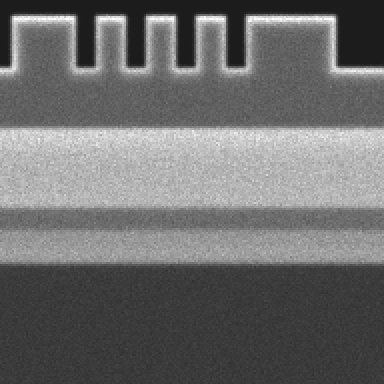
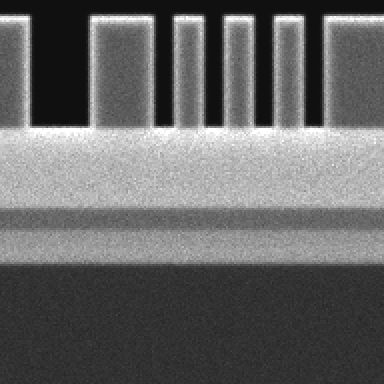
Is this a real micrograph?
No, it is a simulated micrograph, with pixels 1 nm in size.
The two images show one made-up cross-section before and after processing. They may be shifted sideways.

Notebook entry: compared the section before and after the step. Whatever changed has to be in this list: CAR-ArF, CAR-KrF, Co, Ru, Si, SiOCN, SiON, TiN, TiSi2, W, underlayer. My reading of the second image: underlayer removed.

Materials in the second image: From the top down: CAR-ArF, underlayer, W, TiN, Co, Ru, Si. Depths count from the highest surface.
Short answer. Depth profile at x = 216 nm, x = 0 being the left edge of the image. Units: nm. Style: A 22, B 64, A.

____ empty 112, W 80, TiN 22, Co 18, Ru 16, Si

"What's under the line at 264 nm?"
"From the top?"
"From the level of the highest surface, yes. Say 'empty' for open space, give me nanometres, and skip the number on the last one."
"empty 112, W 80, TiN 22, Co 18, Ru 16, Si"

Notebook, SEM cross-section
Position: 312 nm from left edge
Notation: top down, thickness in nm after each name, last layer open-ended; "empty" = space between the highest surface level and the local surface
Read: empty 112, W 80, TiN 22, Co 18, Ru 16, Si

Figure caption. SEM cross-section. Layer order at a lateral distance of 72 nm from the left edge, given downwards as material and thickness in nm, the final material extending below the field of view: empty 112, W 80, TiN 22, Co 18, Ru 16, Si